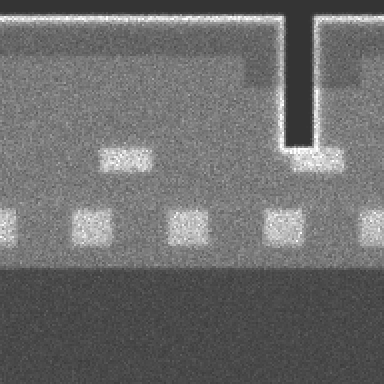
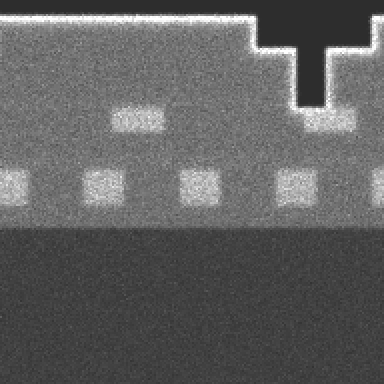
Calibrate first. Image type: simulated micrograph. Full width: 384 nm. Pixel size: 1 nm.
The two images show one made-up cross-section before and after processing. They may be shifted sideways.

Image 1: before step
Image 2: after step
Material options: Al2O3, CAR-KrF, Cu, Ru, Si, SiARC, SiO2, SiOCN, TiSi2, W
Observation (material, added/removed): SiARC, removed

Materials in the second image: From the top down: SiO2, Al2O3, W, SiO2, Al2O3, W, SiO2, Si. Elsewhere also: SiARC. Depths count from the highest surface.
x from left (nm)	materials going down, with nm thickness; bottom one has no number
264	empty 32, SiO2 52, Al2O3 8, SiO2 48, Al2O3 14, SiO2 58, Si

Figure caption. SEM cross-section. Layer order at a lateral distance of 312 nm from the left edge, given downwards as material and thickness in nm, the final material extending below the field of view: empty 92, W 24, SiO2 24, Al2O3 14, W 36, SiO2 22, Si